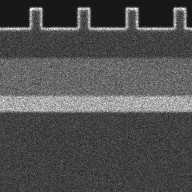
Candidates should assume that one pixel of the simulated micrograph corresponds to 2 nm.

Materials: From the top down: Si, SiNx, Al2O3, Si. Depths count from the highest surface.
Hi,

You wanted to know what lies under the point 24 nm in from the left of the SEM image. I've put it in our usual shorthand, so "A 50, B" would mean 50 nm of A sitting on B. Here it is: empty 40, Si 60, SiNx 76, Al2O3 32, Si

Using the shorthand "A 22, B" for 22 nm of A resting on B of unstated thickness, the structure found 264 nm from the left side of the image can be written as Si 100, SiNx 76, Al2O3 32, Si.